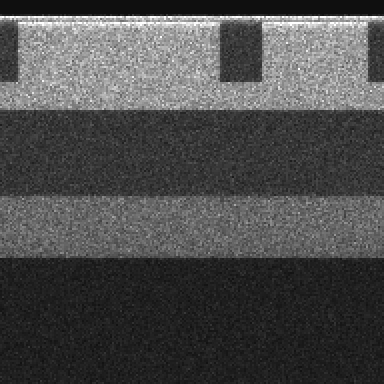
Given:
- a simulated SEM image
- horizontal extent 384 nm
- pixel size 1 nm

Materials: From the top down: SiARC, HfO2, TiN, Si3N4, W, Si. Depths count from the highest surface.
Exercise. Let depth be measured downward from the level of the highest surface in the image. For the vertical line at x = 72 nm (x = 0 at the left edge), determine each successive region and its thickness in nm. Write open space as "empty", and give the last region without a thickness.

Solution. SiARC 6, HfO2 88, TiN 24, Si3N4 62, W 62, Si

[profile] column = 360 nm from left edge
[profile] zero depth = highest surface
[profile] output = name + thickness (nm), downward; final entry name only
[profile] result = SiARC 6, HfO2 88, TiN 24, Si3N4 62, W 62, Si